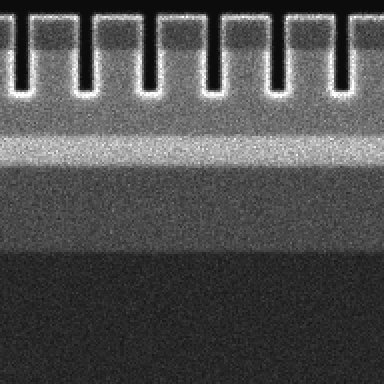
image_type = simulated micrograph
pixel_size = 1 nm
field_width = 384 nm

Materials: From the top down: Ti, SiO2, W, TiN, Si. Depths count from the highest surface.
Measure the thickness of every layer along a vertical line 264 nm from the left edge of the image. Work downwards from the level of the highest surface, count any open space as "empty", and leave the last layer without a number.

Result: Ti 34, SiO2 86, W 30, TiN 86, Si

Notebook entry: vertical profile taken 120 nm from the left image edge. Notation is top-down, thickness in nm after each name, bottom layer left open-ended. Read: Ti 34, SiO2 86, W 30, TiN 86, Si